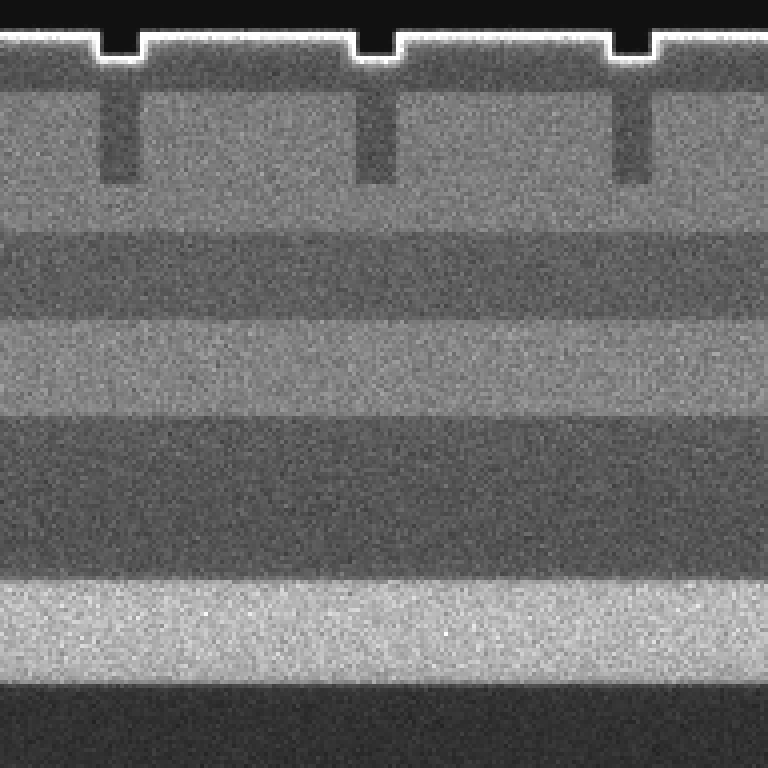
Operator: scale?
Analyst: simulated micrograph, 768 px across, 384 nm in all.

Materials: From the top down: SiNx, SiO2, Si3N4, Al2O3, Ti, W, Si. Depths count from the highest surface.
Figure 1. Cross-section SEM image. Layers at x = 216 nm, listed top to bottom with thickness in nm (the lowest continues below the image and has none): SiNx 30, SiO2 70, Si3N4 44, Al2O3 48, Ti 82, W 52, Si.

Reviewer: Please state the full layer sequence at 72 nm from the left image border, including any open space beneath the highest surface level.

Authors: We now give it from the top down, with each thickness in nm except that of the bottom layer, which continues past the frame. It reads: SiNx 30, SiO2 70, Si3N4 44, Al2O3 48, Ti 82, W 52, Si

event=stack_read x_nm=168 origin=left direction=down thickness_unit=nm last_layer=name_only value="SiNx 30, SiO2 70, Si3N4 44, Al2O3 48, Ti 82, W 52, Si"